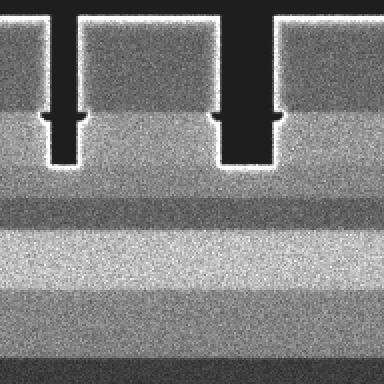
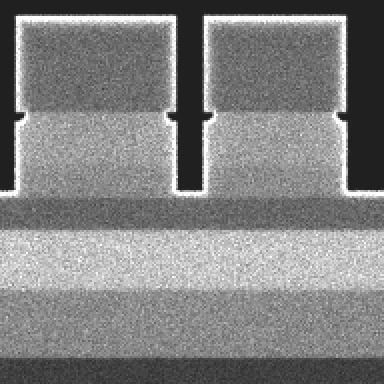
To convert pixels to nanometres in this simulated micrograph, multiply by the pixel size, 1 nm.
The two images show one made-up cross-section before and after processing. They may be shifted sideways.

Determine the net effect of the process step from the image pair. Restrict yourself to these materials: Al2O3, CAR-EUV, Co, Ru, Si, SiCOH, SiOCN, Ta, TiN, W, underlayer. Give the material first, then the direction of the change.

Co: removed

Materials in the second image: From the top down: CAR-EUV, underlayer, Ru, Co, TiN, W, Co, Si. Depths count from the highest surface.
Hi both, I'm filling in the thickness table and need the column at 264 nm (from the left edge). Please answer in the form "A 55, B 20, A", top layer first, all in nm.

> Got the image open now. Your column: CAR-EUV 36, underlayer 60, Ru 54, Co 32, TiN 32, W 60, Co 68, Si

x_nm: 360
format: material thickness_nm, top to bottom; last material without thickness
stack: empty 176, Co 6, TiN 32, W 60, Co 68, Si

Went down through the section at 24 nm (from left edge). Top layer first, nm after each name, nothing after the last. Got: CAR-EUV 36, underlayer 60, empty 6, Ru 48, Co 32, TiN 32, W 60, Co 68, Si